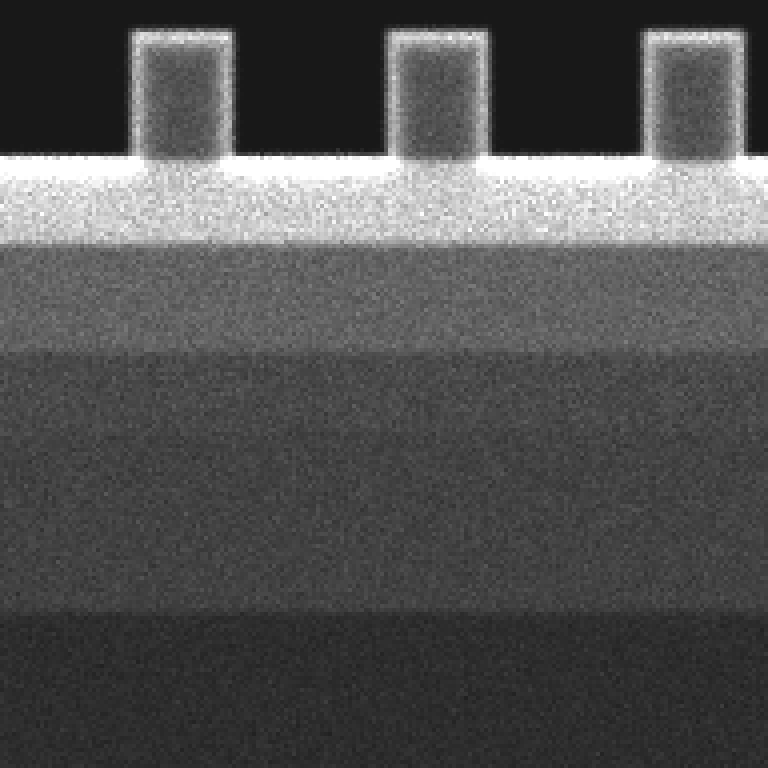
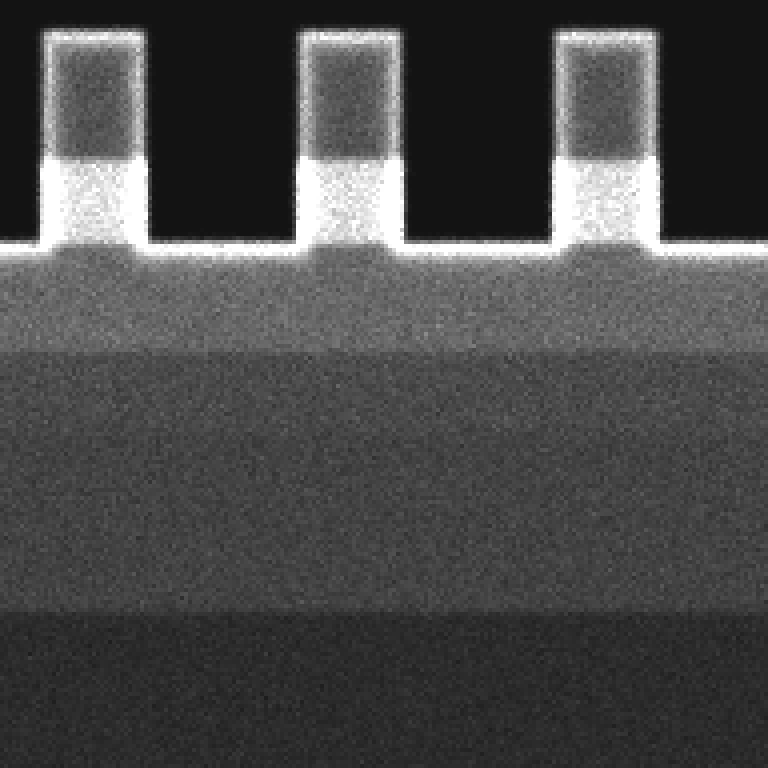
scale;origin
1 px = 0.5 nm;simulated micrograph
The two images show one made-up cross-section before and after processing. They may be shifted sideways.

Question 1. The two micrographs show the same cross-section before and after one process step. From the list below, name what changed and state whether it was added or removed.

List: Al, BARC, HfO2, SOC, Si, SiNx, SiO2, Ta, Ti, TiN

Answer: HfO2, removed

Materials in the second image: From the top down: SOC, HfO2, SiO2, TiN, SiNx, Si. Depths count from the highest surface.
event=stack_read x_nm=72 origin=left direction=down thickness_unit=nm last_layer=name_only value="empty 106, SiO2 54, TiN 40, SiNx 90, Si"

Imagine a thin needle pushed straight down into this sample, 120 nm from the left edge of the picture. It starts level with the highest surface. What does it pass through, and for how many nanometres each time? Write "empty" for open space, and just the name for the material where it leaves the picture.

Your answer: empty 106, SiO2 54, TiN 40, SiNx 90, Si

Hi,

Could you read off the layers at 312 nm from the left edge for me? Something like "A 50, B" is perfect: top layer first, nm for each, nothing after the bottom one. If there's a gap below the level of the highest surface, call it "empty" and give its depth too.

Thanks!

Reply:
SOC 64, HfO2 42, SiO2 54, TiN 40, SiNx 90, Si